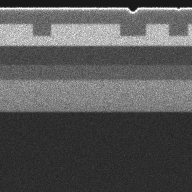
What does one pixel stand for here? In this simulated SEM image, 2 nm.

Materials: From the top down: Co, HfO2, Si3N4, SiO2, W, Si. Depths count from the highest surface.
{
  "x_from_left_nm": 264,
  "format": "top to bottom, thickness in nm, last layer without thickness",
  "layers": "empty 8, Co 48, HfO2 20, Si3N4 38, SiO2 30, W 64, Si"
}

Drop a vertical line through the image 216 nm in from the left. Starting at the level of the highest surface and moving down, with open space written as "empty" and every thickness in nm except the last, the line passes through Co 32, HfO2 44, Si3N4 38, SiO2 30, W 64, Si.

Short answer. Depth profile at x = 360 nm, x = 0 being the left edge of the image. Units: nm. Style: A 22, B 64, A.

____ Co 56, HfO2 20, Si3N4 38, SiO2 30, W 64, Si